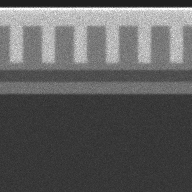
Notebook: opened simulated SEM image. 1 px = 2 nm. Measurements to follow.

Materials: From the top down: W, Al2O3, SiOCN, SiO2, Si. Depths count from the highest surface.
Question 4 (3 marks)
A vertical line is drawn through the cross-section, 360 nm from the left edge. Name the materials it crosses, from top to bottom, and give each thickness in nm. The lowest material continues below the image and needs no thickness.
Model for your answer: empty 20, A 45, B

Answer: W 110, Al2O3 14, SiOCN 24, SiO2 24, Si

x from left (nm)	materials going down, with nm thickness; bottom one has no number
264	W 36, Al2O3 88, SiOCN 24, SiO2 24, Si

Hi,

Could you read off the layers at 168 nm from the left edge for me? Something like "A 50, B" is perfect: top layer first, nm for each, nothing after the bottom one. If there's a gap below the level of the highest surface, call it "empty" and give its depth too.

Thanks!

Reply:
W 110, Al2O3 14, SiOCN 24, SiO2 24, Si